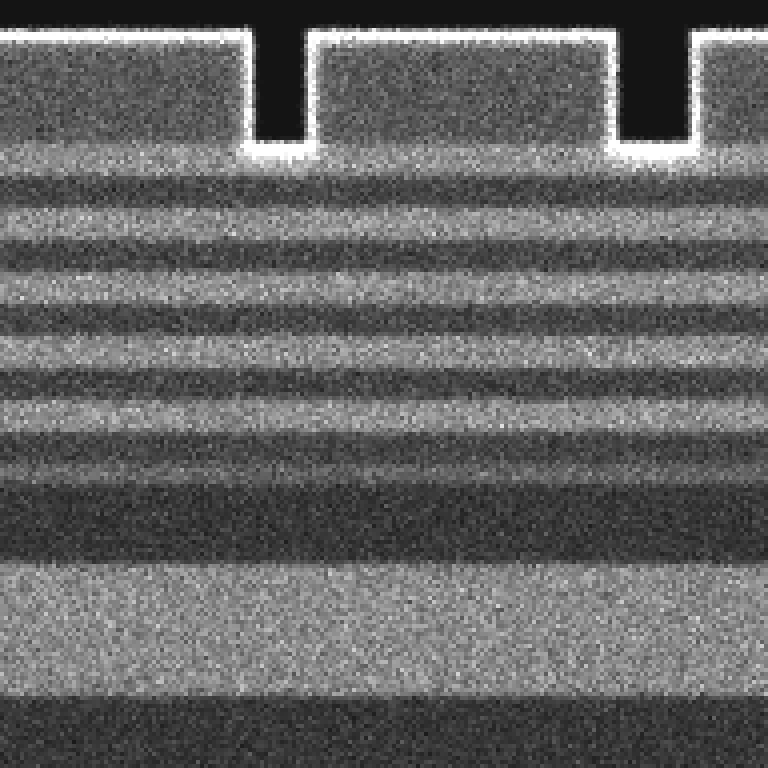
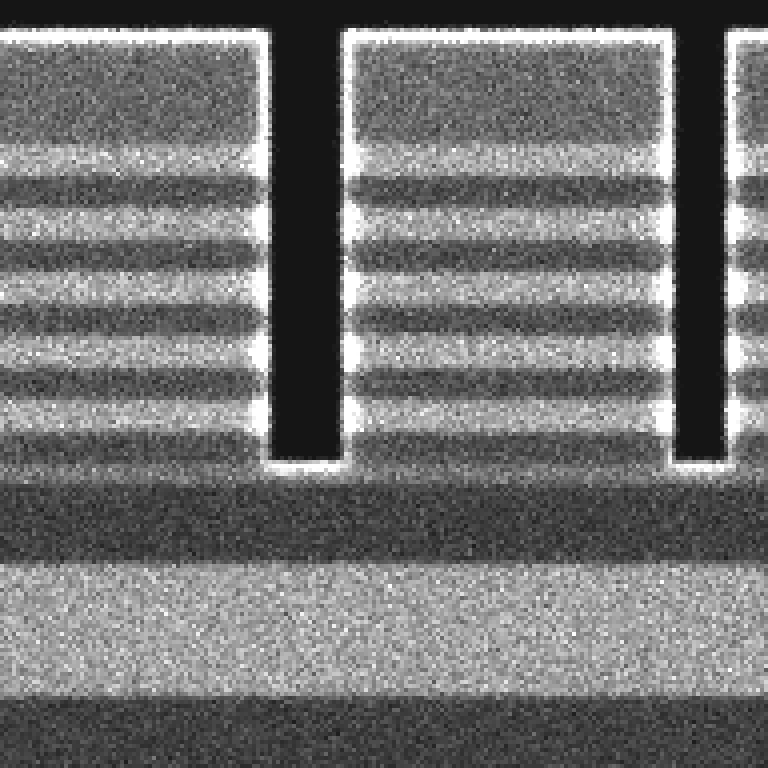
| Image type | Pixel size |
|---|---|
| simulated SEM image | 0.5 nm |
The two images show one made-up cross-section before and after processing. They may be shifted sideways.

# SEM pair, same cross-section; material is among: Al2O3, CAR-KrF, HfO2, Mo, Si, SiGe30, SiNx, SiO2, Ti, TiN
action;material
removed;Al2O3 and SiGe30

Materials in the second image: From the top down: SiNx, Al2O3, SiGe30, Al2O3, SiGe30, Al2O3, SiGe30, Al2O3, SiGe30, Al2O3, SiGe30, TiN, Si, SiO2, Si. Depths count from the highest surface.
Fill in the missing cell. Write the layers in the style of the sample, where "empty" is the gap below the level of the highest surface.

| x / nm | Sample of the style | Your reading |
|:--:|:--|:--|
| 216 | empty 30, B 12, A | SiNx 56, Al2O3 16, SiGe30 16, Al2O3 16, SiGe30 16, Al2O3 16, SiGe30 16, Al2O3 16, SiGe30 16, Al2O3 16, SiGe30 16, TiN 10, Si 40, SiO2 66, Si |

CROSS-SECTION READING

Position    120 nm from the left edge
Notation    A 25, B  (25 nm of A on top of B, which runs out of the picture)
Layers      SiNx 56, Al2O3 16, SiGe30 16, Al2O3 16, SiGe30 16, Al2O3 16, SiGe30 16, Al2O3 16, SiGe30 16, Al2O3 16, SiGe30 16, TiN 10, Si 40, SiO2 66, Si